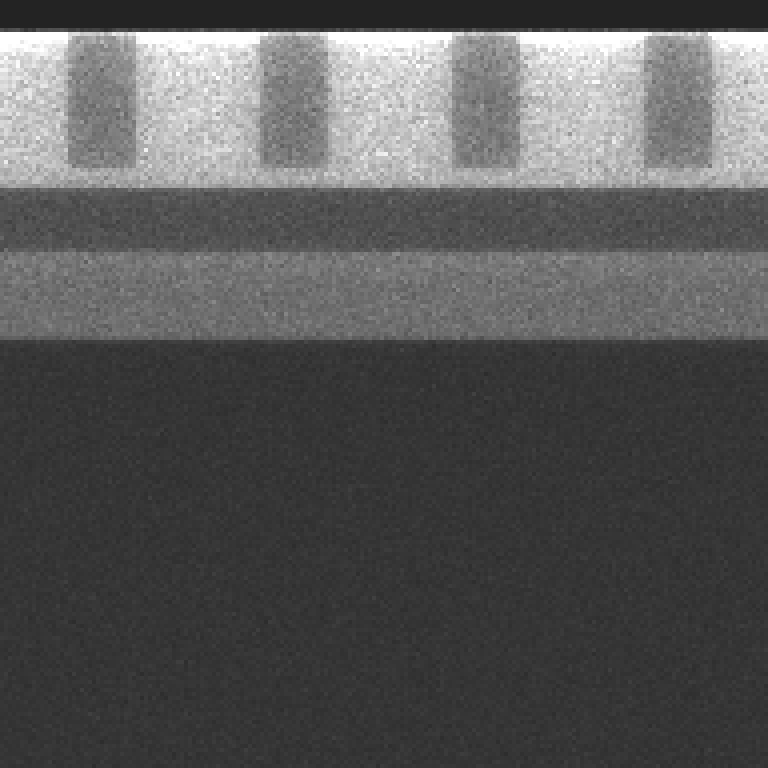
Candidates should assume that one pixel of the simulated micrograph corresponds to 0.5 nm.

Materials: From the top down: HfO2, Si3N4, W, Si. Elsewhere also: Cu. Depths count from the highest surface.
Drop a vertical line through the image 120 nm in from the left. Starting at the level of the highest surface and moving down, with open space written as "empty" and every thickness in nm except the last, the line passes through HfO2 78, Si3N4 32, W 44, Si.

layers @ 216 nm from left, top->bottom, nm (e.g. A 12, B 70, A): HfO2 78, Si3N4 32, W 44, Si